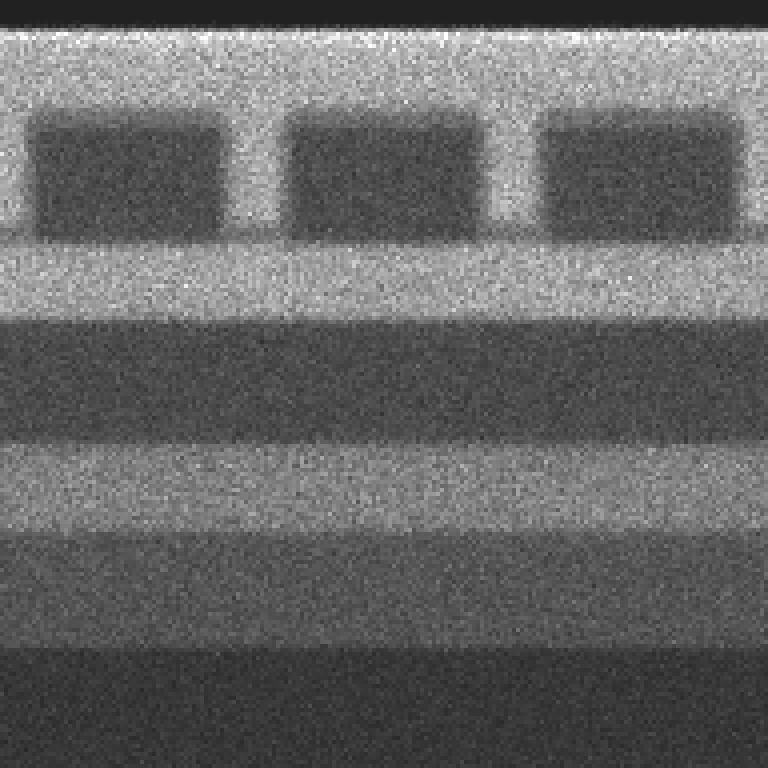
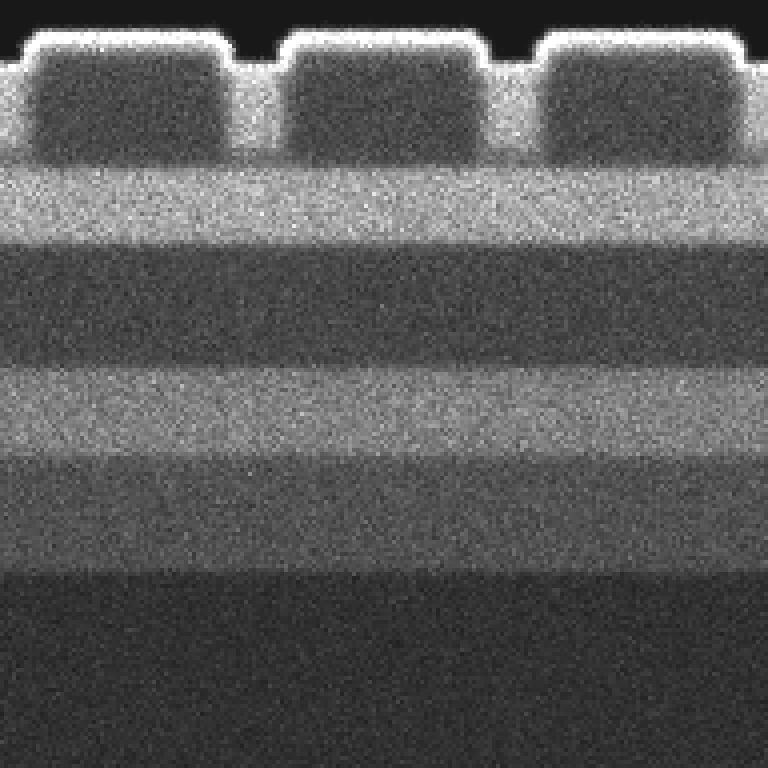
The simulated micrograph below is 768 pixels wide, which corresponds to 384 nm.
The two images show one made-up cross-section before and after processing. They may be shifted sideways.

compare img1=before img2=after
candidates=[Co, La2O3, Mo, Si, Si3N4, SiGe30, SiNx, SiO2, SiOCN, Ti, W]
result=removed:W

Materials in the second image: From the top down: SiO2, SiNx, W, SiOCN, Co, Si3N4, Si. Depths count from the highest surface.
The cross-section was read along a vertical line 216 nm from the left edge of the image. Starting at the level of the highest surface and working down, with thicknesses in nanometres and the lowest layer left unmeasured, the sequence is SiO2 10, SiNx 58, W 38, SiOCN 62, Co 44, Si3N4 58, Si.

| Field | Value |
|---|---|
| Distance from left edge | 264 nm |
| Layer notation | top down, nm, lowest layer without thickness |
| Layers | empty 16, W 42, SiO2 10, W 38, SiOCN 62, Co 44, Si3N4 58, Si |